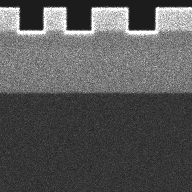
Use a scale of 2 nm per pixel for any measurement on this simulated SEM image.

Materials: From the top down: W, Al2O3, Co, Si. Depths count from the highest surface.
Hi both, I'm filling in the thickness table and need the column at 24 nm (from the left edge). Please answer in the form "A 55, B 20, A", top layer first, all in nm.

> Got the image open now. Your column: W 46, Al2O3 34, Co 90, Si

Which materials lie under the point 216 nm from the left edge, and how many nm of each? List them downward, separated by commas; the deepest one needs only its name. W 46, Al2O3 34, Co 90, Si